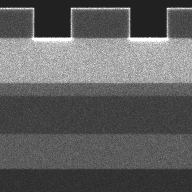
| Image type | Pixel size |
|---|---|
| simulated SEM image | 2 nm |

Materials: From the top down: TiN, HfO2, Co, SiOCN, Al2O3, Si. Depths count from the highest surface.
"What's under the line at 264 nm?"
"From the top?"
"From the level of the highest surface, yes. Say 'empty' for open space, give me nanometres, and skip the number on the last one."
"empty 60, HfO2 90, Co 26, SiOCN 76, Al2O3 70, Si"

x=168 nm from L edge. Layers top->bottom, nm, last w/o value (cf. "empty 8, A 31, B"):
TiN 60, HfO2 90, Co 26, SiOCN 76, Al2O3 70, Si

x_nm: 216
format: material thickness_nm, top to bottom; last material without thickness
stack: TiN 60, HfO2 90, Co 26, SiOCN 76, Al2O3 70, Si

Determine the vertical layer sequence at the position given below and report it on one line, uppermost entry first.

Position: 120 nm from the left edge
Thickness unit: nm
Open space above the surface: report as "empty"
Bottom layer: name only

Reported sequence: empty 60, HfO2 90, Co 26, SiOCN 76, Al2O3 70, Si